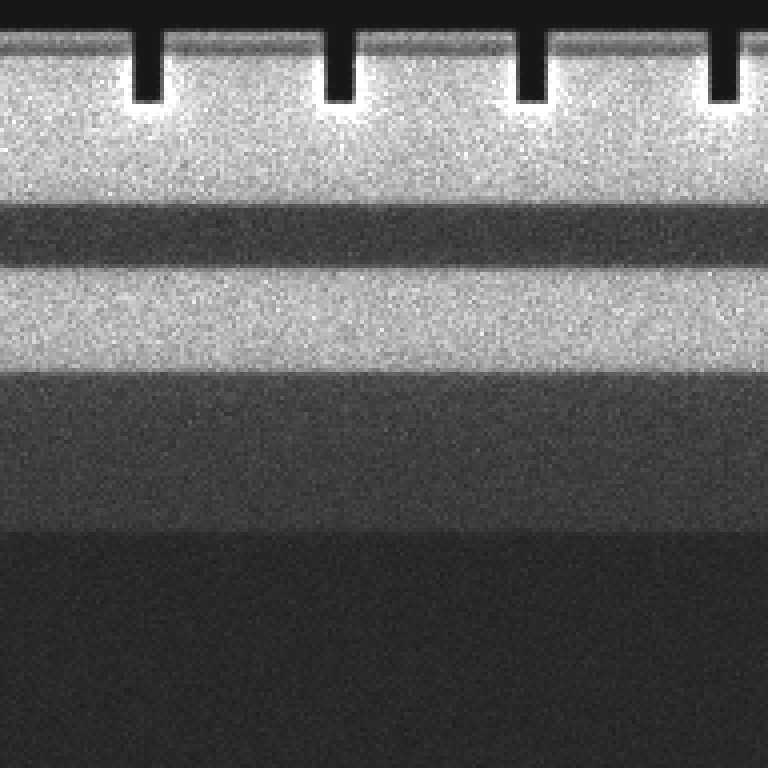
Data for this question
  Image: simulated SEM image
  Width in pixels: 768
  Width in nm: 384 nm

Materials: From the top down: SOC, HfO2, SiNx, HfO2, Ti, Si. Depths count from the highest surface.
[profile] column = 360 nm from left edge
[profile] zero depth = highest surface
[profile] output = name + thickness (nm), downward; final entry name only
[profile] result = empty 36, HfO2 50, SiNx 32, HfO2 52, Ti 80, Si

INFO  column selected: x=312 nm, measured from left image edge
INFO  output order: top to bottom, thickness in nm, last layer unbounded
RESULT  SOC 12, HfO2 74, SiNx 32, HfO2 52, Ti 80, Si